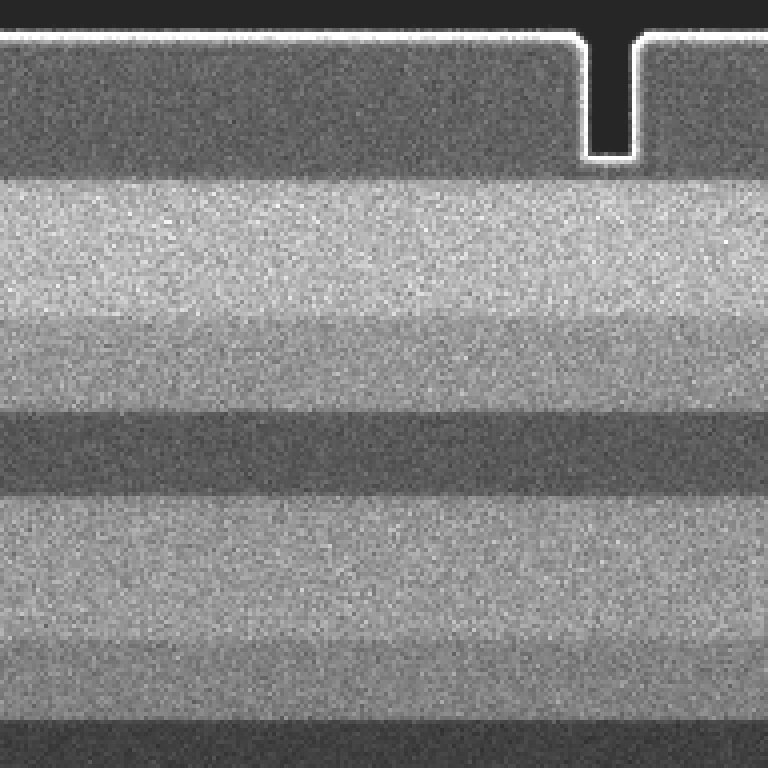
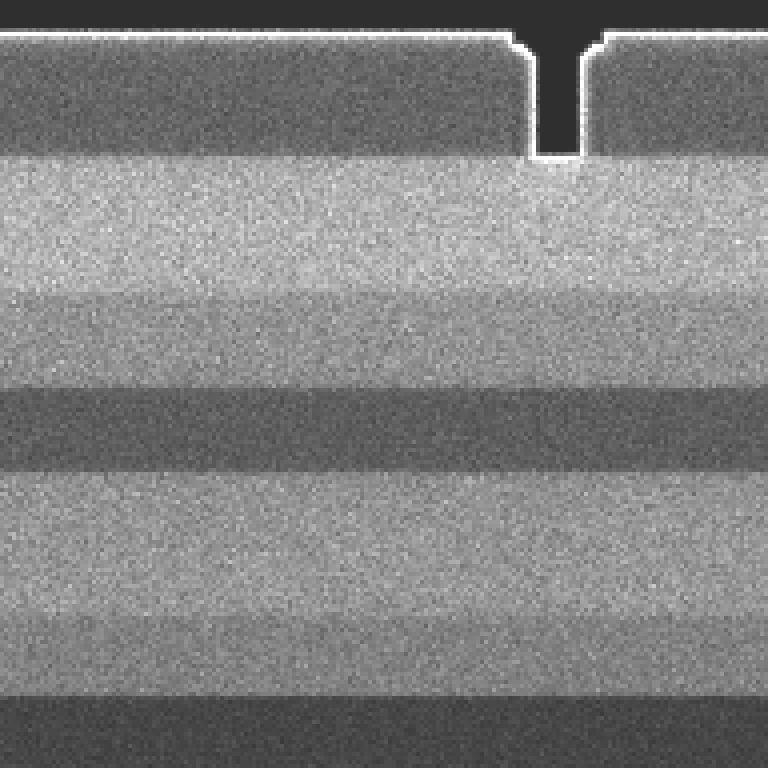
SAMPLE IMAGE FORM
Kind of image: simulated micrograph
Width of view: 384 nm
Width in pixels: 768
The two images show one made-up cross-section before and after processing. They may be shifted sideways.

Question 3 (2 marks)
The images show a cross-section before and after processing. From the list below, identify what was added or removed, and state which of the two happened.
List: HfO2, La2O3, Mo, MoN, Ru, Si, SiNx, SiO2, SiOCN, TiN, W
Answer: SiOCN was removed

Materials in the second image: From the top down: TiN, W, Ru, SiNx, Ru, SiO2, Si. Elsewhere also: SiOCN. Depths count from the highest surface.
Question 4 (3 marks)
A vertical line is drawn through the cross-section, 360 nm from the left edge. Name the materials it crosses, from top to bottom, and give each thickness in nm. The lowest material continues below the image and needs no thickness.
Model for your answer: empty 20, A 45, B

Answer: TiN 62, W 68, Ru 48, SiNx 42, Ru 72, SiO2 40, Si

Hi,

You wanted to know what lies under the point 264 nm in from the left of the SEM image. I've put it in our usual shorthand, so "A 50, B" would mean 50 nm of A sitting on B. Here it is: empty 10, SiOCN 52, W 68, Ru 48, SiNx 42, Ru 72, SiO2 40, Si